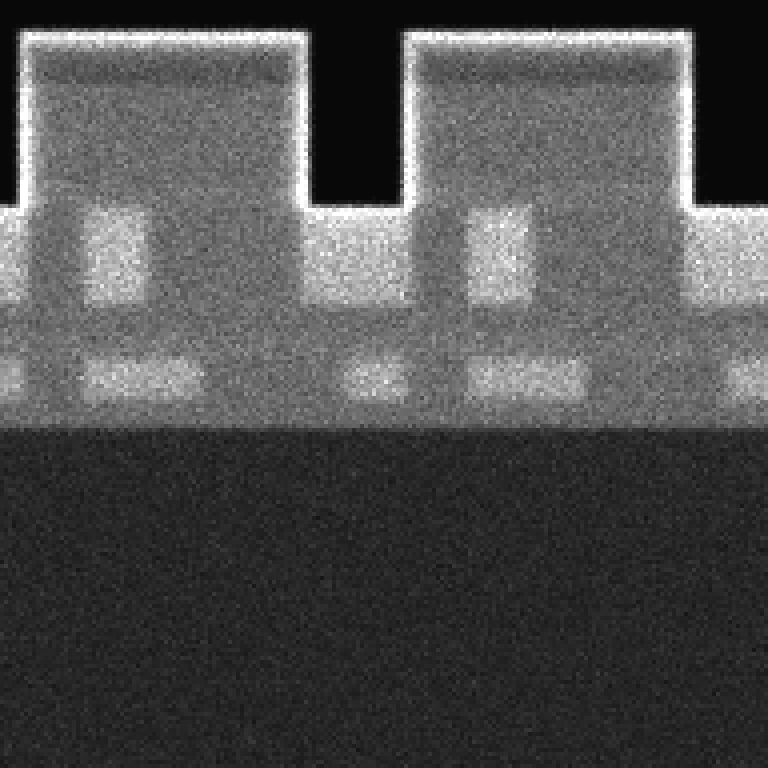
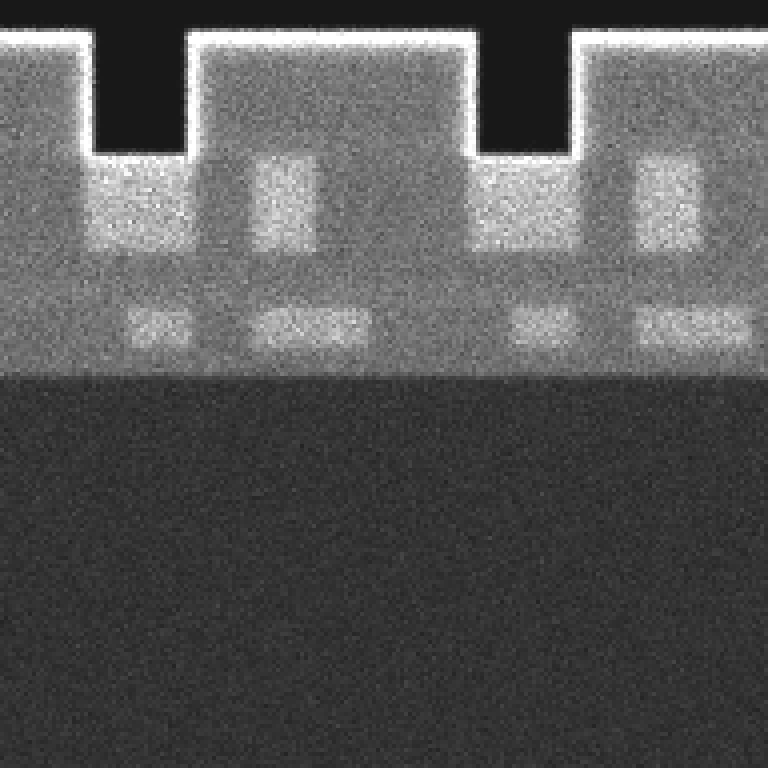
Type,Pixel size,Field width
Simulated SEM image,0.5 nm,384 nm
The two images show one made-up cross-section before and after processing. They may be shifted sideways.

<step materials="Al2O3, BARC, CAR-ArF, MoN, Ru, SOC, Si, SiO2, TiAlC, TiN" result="removed SOC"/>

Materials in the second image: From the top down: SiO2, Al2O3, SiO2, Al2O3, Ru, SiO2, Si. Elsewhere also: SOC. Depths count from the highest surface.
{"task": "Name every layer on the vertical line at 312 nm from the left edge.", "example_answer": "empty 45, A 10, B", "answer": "SiO2 50, Al2O3 12, SiO2 62, Al2O3 14, SiO2 34, Si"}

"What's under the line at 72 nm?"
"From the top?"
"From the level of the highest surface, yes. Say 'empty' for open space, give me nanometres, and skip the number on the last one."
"empty 62, Ru 48, SiO2 14, Al2O3 14, Ru 20, SiO2 14, Si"